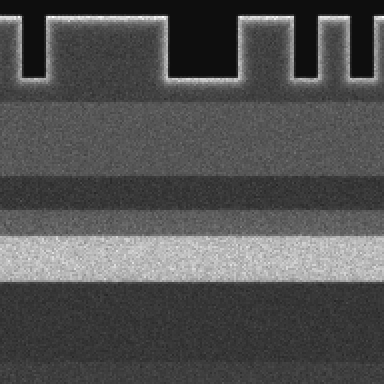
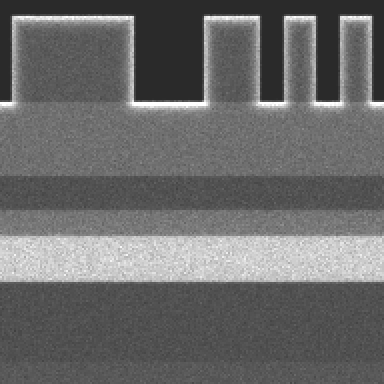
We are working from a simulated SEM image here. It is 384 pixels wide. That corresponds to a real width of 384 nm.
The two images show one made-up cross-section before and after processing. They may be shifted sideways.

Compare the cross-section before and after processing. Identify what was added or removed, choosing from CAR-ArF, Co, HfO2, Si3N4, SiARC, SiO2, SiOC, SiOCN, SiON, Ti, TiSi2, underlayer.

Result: underlayer removed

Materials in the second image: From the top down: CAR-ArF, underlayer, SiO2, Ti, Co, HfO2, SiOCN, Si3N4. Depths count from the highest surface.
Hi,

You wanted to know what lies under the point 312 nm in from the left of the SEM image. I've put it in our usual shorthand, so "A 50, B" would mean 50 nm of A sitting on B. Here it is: CAR-ArF 62, underlayer 24, SiO2 74, Ti 34, Co 26, HfO2 46, SiOCN 80, Si3N4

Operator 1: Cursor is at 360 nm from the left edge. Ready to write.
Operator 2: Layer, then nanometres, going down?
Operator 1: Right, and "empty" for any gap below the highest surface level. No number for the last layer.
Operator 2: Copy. CAR-ArF 62, underlayer 24, SiO2 74, Ti 34, Co 26, HfO2 46, SiOCN 80, Si3N4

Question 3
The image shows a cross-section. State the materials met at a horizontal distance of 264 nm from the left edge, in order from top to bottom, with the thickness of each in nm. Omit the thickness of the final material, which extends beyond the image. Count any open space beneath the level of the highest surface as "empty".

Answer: empty 86, SiO2 74, Ti 34, Co 26, HfO2 46, SiOCN 80, Si3N4